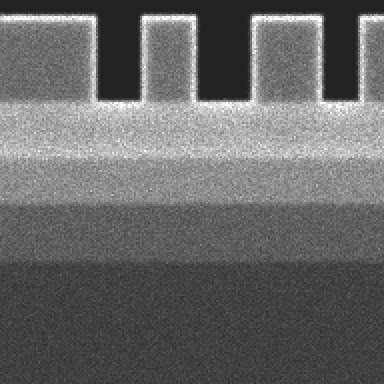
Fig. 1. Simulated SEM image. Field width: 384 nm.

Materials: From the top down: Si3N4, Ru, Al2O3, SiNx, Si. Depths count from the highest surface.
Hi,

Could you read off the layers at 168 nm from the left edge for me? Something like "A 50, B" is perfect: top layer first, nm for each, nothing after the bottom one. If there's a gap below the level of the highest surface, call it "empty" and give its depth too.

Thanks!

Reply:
Si3N4 86, Ru 56, Al2O3 46, SiNx 58, Si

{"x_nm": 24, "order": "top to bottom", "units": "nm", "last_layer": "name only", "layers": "Si3N4 86, Ru 56, Al2O3 46, SiNx 58, Si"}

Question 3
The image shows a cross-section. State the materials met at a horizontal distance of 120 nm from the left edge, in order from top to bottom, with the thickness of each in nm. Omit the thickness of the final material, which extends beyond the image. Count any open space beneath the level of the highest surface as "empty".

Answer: empty 86, Ru 56, Al2O3 46, SiNx 58, Si